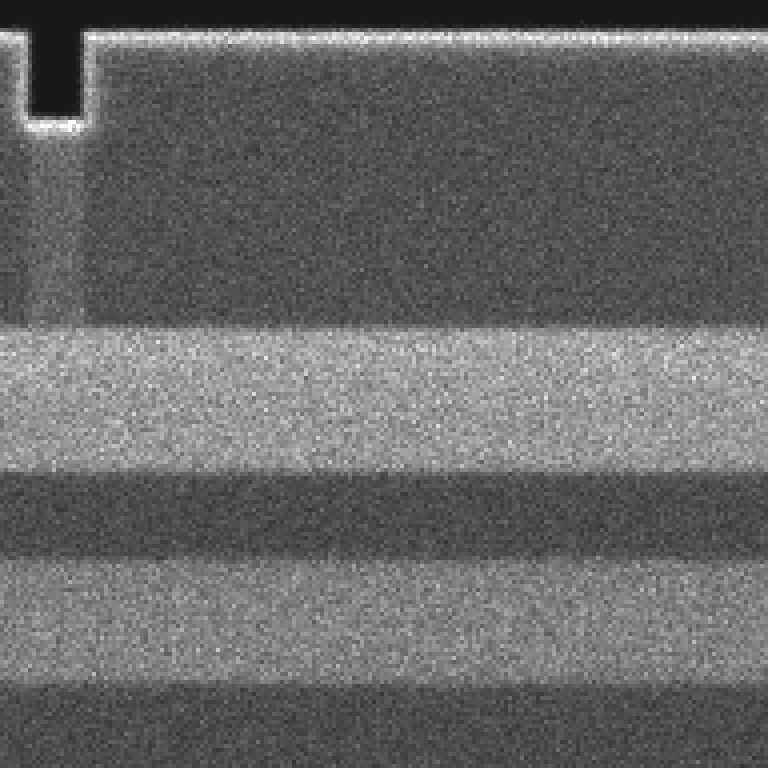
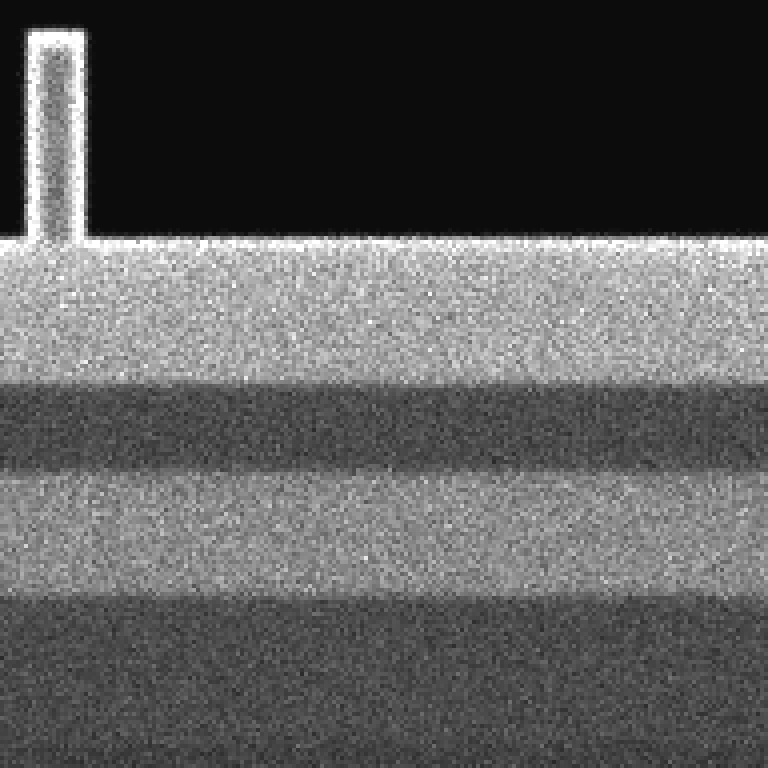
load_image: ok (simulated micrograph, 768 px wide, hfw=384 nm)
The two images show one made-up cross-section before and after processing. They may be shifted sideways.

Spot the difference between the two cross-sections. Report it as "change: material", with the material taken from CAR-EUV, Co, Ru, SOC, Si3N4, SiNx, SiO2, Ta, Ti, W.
removed: SOC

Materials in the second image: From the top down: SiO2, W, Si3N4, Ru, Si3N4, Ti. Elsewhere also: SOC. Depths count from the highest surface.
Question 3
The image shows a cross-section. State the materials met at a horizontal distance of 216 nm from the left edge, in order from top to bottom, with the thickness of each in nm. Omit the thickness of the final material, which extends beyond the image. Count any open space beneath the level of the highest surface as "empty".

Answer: empty 104, W 72, Si3N4 44, Ru 62, Si3N4 74, Ti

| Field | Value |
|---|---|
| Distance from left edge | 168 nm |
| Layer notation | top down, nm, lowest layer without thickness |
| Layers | empty 104, W 72, Si3N4 44, Ru 62, Si3N4 74, Ti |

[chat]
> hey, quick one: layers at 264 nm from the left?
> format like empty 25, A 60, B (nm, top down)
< empty 104, W 72, Si3N4 44, Ru 62, Si3N4 74, Ti